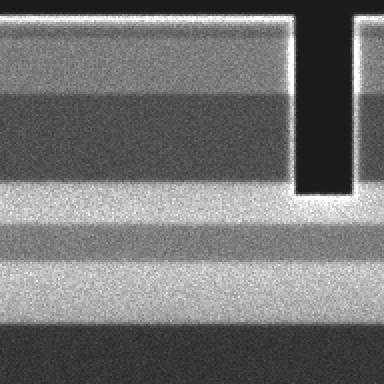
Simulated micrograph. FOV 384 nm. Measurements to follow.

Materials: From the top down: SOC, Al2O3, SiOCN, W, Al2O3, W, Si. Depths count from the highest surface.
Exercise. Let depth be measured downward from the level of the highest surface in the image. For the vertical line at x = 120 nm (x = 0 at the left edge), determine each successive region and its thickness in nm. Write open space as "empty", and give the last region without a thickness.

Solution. SOC 22, Al2O3 56, SiOCN 88, W 42, Al2O3 38, W 62, Si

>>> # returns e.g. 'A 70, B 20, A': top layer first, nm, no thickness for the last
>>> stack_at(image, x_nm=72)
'SOC 22, Al2O3 56, SiOCN 88, W 42, Al2O3 38, W 62, Si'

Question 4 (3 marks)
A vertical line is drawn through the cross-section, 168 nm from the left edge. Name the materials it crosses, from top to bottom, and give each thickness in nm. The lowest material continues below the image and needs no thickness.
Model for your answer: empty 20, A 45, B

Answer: SOC 22, Al2O3 56, SiOCN 88, W 42, Al2O3 38, W 62, Si